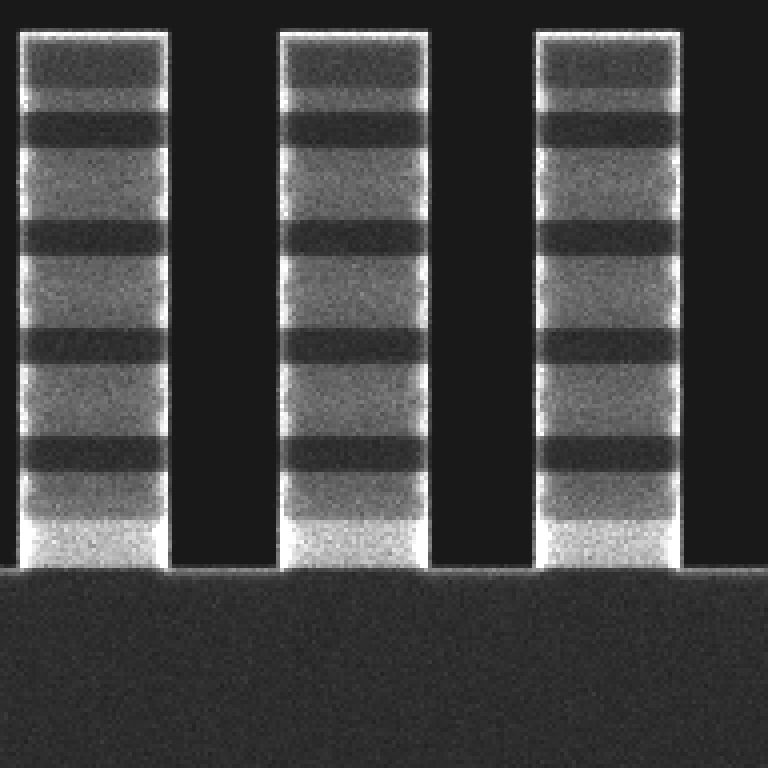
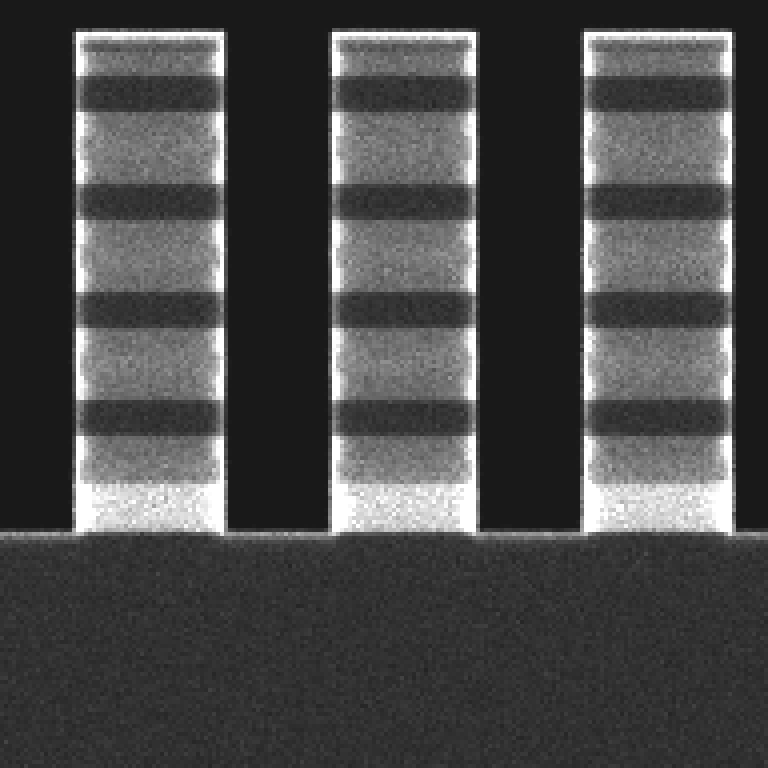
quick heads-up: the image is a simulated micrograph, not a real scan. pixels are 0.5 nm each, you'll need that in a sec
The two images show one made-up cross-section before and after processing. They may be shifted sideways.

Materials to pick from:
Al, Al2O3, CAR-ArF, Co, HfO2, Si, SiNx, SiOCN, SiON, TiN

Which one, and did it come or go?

SiNx - removed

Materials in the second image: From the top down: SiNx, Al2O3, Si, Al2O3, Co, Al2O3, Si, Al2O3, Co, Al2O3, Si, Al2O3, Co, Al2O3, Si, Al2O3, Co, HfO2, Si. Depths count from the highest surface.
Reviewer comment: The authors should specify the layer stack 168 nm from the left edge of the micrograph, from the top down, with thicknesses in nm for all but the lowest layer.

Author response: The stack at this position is SiNx 10, Al2O3 12, Si 18, Al2O3 12, Co 12, Al2O3 12, Si 18, Al2O3 12, Co 12, Al2O3 12, Si 18, Al2O3 12, Co 12, Al2O3 12, Si 18, Al2O3 12, Co 12, HfO2 24, Si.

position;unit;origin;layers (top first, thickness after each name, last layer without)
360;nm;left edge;SiNx 10, Al2O3 12, Si 18, Al2O3 12, Co 12, Al2O3 12, Si 18, Al2O3 12, Co 12, Al2O3 12, Si 18, Al2O3 12, Co 12, Al2O3 12, Si 18, Al2O3 12, Co 12, HfO2 24, Si